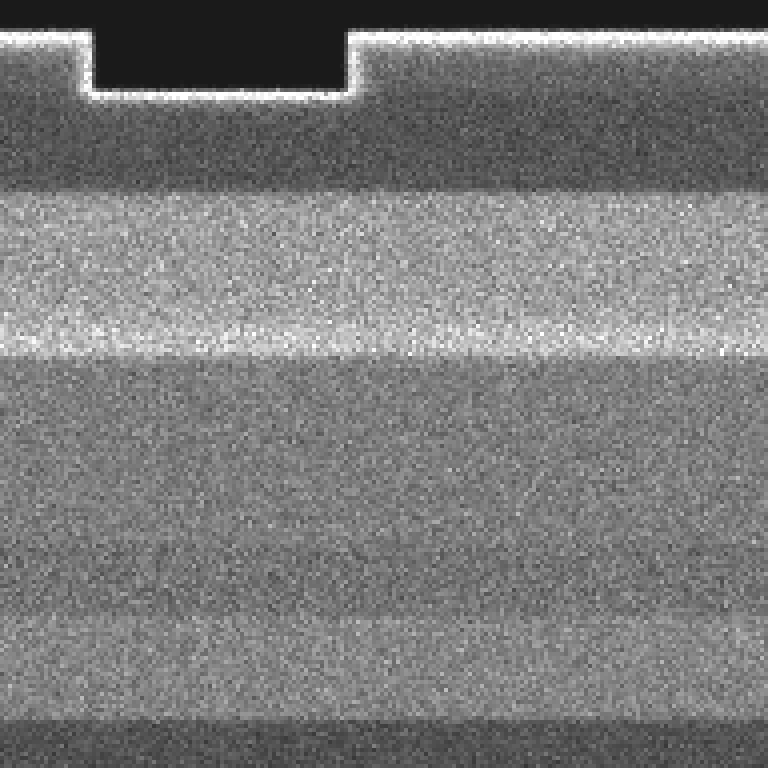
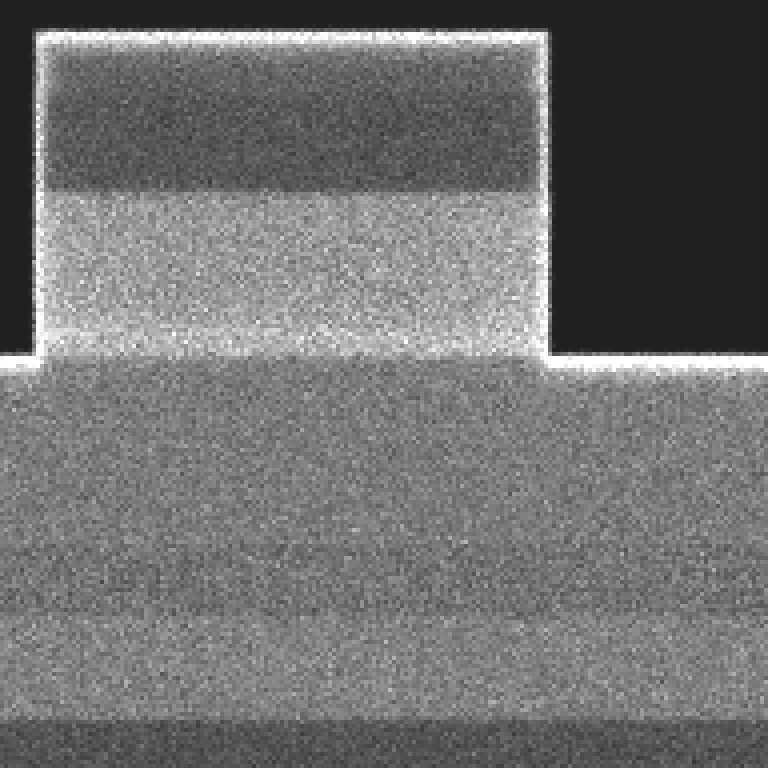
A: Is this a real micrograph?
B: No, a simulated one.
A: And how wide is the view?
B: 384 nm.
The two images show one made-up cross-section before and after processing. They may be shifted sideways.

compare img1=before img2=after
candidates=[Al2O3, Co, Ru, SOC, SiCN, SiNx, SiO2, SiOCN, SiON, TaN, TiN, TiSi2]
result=removed:Co and Ru and SiNx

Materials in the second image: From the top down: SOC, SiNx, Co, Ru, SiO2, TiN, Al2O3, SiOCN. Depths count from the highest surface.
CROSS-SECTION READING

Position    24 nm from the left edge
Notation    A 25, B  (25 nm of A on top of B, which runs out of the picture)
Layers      SOC 30, SiNx 50, Co 66, Ru 16, SiO2 94, TiN 36, Al2O3 52, SiOCN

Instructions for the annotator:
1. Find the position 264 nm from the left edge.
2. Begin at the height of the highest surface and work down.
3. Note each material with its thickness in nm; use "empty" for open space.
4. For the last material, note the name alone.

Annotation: SOC 30, SiNx 50, Co 66, Ru 16, SiO2 94, TiN 36, Al2O3 52, SiOCN